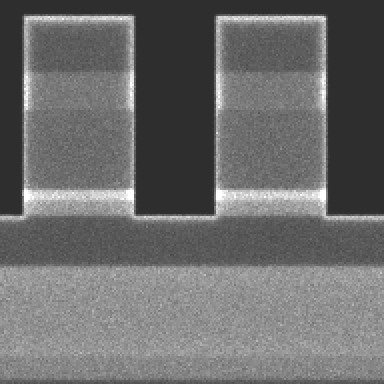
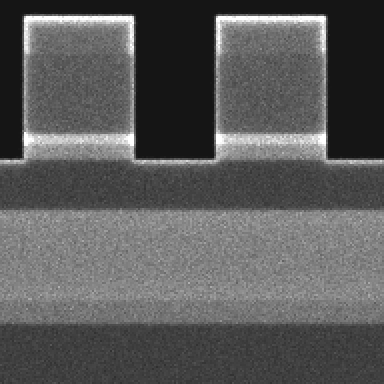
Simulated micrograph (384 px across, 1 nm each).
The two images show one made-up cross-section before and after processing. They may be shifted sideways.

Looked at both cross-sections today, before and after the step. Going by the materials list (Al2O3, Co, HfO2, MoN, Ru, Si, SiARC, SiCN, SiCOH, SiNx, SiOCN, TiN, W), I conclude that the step removed SiARC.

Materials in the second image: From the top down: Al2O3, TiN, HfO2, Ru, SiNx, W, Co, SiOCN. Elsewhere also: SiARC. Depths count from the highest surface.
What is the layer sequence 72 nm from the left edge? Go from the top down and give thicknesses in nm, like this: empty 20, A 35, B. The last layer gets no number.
Al2O3 38, TiN 80, HfO2 10, Ru 16, SiNx 50, W 90, Co 24, SiOCN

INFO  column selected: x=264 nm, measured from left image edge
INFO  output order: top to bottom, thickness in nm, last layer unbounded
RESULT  Al2O3 38, TiN 80, HfO2 10, Ru 16, SiNx 50, W 90, Co 24, SiOCN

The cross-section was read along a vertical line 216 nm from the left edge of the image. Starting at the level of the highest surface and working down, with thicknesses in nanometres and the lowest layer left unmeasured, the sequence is Al2O3 38, TiN 80, HfO2 10, Ru 16, SiNx 50, W 90, Co 24, SiOCN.